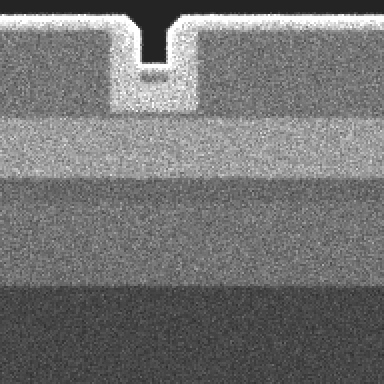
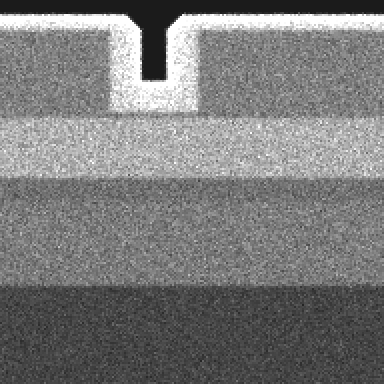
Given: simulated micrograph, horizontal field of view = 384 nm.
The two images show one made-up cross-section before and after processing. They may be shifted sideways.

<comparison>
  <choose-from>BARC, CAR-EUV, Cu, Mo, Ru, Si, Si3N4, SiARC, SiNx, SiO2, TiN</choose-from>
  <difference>SiARC removed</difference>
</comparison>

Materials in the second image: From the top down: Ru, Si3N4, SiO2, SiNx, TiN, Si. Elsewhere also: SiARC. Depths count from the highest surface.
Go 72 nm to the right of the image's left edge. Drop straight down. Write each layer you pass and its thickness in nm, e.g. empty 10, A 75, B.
Ru 14, Si3N4 88, SiO2 60, SiNx 24, TiN 84, Si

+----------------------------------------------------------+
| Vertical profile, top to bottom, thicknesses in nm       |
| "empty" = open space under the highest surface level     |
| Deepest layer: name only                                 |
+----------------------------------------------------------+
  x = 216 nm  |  Ru 14, Si3N4 88, SiO2 60, SiNx 24, TiN 84, Si